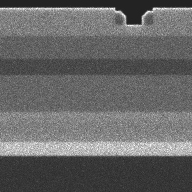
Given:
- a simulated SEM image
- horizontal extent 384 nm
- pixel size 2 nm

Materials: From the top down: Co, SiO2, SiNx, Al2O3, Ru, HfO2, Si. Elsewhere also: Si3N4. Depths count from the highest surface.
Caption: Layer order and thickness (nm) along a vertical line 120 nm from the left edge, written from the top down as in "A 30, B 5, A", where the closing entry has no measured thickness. Co 56, SiO2 46, SiNx 32, Al2O3 74, Ru 60, HfO2 28, Si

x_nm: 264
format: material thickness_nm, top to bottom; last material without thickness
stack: empty 34, Co 22, SiO2 46, SiNx 32, Al2O3 74, Ru 60, HfO2 28, Si